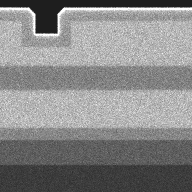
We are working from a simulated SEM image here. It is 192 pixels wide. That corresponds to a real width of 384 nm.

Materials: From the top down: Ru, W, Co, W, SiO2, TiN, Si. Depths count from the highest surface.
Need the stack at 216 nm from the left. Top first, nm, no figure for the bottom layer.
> Ru 26, W 90, Co 48, W 76, SiO2 24, TiN 50, Si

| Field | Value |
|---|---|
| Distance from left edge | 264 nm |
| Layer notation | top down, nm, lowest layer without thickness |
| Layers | Ru 26, W 90, Co 48, W 76, SiO2 24, TiN 50, Si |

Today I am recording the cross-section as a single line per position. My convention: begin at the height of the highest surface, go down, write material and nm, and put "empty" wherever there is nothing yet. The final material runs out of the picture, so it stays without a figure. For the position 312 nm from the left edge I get Ru 26, W 90, Co 48, W 76, SiO2 24, TiN 50, Si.